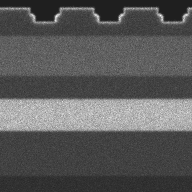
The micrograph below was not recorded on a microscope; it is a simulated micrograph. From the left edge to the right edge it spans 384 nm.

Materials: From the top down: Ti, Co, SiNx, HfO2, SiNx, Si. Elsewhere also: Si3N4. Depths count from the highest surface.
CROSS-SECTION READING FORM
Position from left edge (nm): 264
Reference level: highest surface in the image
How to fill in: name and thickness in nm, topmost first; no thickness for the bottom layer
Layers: Ti 56, Co 80, SiNx 46, HfO2 64, SiNx 90, Si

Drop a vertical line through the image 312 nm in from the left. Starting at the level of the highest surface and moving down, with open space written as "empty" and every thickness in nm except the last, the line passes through Ti 56, Co 80, SiNx 46, HfO2 64, SiNx 90, Si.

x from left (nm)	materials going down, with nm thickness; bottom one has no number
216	empty 28, Ti 28, Co 80, SiNx 46, HfO2 64, SiNx 90, Si